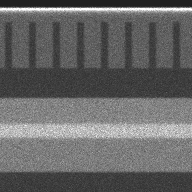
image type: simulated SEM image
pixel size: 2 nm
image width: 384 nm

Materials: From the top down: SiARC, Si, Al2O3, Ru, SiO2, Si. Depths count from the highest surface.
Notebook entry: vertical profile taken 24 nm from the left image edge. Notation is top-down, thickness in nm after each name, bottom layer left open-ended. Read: SiARC 120, Si 60, Al2O3 52, Ru 28, SiO2 68, Si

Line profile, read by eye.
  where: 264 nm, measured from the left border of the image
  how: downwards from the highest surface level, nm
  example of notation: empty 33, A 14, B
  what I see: SiARC 120, Si 60, Al2O3 52, Ru 28, SiO2 68, Si